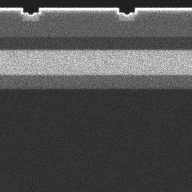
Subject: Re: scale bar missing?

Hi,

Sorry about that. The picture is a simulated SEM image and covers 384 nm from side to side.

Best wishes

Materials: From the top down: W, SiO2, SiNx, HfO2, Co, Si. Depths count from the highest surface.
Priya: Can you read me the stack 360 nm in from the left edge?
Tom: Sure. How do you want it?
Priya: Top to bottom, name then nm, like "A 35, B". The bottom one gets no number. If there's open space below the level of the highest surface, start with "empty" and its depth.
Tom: SiO2 58, SiNx 26, HfO2 50, Co 28, Si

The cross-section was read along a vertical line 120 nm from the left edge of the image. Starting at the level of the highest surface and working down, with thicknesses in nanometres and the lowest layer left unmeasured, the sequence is SiO2 58, SiNx 26, HfO2 50, Co 28, Si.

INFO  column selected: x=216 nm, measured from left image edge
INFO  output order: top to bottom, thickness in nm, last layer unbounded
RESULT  SiO2 58, SiNx 26, HfO2 50, Co 28, Si